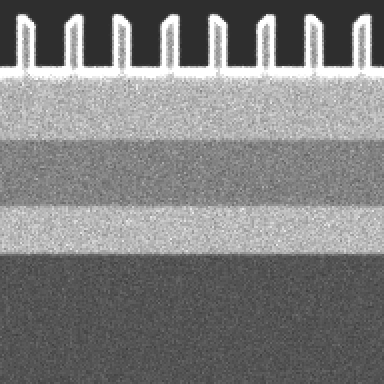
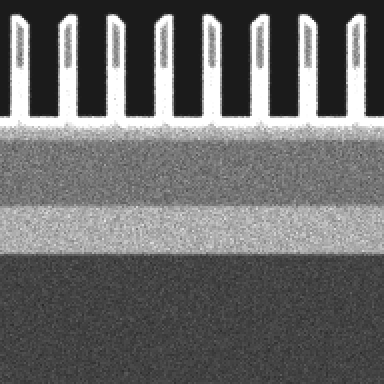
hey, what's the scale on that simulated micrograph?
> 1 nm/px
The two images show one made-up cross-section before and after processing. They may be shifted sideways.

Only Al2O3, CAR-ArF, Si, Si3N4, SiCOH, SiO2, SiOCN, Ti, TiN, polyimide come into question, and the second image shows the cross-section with SiO2 removed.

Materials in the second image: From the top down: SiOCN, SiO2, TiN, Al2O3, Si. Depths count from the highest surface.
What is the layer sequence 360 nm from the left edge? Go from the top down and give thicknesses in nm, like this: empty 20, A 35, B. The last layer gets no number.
SiOCN 52, SiO2 72, TiN 66, Al2O3 48, Si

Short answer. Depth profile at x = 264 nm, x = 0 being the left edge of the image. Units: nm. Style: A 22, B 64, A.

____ SiOCN 52, SiO2 72, TiN 66, Al2O3 48, Si